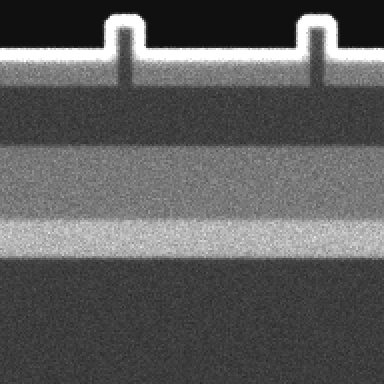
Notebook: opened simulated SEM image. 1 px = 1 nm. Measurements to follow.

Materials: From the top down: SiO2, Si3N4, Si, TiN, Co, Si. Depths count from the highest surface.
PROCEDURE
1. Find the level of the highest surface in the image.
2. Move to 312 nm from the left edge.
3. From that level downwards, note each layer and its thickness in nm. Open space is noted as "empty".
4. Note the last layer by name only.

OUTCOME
SiO2 12, Si 118, TiN 74, Co 38, Si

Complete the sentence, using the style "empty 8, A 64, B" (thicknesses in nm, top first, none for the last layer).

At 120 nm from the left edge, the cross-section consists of SiO2 12, Si 118, TiN 74, Co 38, Si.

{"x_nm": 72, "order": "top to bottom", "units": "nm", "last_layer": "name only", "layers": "empty 34, SiO2 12, Si3N4 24, Si 60, TiN 74, Co 38, Si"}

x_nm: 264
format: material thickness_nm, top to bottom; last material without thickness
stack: empty 34, SiO2 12, Si3N4 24, Si 60, TiN 74, Co 38, Si